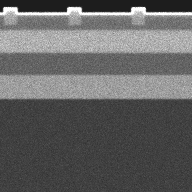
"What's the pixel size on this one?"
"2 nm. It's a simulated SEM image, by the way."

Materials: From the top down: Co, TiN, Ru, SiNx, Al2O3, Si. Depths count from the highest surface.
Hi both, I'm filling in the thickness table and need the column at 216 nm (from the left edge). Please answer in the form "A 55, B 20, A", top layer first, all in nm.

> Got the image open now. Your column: empty 10, TiN 34, Ru 46, SiNx 44, Al2O3 48, Si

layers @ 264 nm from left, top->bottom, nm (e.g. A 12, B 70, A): Co 34, TiN 10, Ru 46, SiNx 44, Al2O3 48, Si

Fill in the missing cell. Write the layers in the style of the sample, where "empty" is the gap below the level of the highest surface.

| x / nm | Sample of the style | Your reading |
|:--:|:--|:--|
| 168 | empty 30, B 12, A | empty 10, TiN 34, Ru 46, SiNx 44, Al2O3 48, Si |